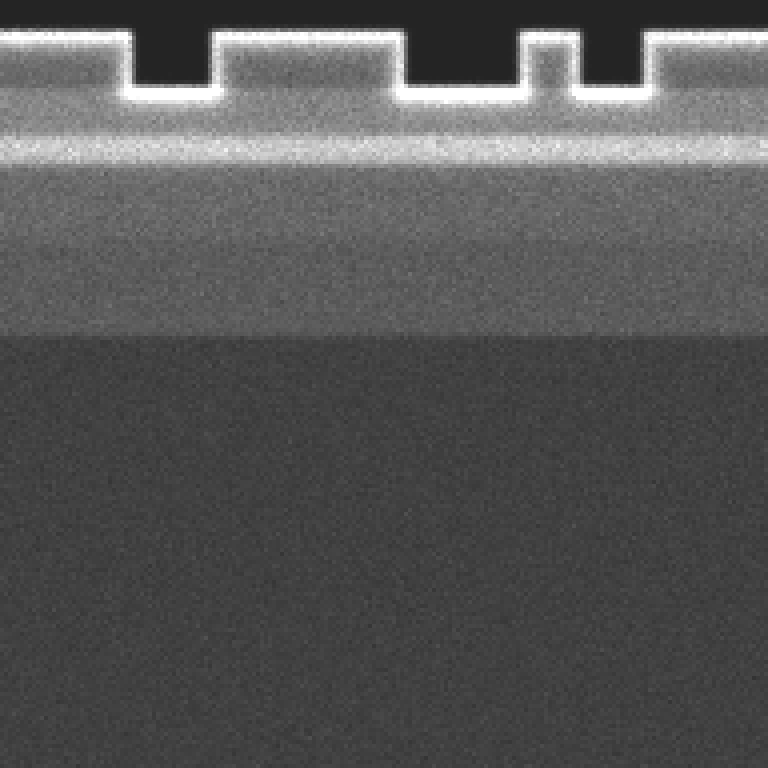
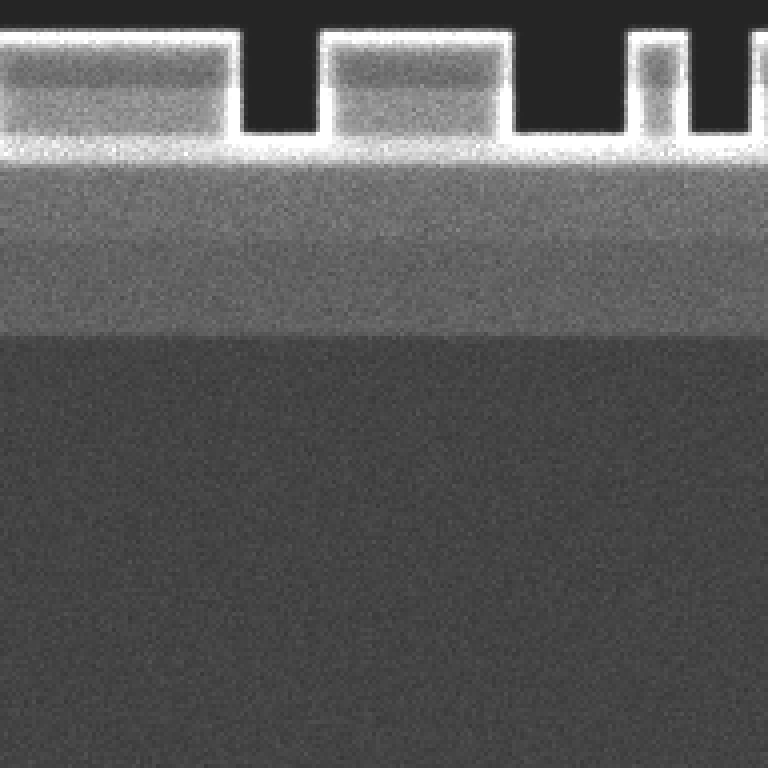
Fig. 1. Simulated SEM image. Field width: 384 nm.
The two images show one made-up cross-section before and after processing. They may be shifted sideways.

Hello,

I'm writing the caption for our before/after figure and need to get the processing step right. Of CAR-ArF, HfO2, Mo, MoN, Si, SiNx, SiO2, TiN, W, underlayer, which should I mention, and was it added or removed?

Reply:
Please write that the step removed SiO2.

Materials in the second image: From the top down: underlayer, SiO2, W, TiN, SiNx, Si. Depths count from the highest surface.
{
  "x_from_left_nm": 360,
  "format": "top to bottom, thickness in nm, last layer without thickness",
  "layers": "empty 52, W 14, TiN 38, SiNx 48, Si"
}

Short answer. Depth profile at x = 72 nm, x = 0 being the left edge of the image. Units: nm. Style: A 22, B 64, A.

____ underlayer 28, SiO2 24, W 14, TiN 38, SiNx 48, Si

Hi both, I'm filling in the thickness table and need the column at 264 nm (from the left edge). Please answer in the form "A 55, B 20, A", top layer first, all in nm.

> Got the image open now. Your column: empty 52, W 14, TiN 38, SiNx 48, Si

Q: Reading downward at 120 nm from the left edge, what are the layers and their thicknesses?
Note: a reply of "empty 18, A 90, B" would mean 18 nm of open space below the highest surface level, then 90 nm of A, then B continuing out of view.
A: empty 52, W 14, TiN 38, SiNx 48, Si